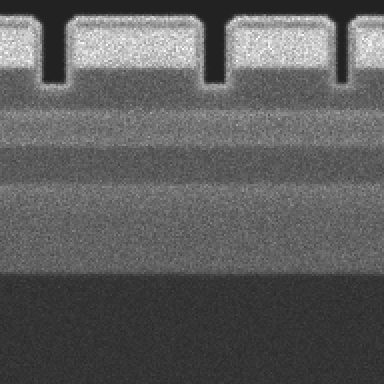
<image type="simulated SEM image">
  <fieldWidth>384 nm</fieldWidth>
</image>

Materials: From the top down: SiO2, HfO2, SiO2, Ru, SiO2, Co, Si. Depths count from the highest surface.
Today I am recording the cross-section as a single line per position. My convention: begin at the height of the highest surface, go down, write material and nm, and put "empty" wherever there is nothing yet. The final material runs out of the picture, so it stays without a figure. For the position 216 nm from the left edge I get empty 68, SiO2 26, Ru 36, SiO2 38, Co 90, Si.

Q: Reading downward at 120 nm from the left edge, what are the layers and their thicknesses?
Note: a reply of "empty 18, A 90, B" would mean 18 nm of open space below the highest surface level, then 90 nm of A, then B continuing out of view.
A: SiO2 12, HfO2 40, SiO2 42, Ru 36, SiO2 38, Co 90, Si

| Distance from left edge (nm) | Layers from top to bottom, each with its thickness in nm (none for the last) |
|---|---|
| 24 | SiO2 12, HfO2 40, SiO2 42, Ru 36, SiO2 38, Co 90, Si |